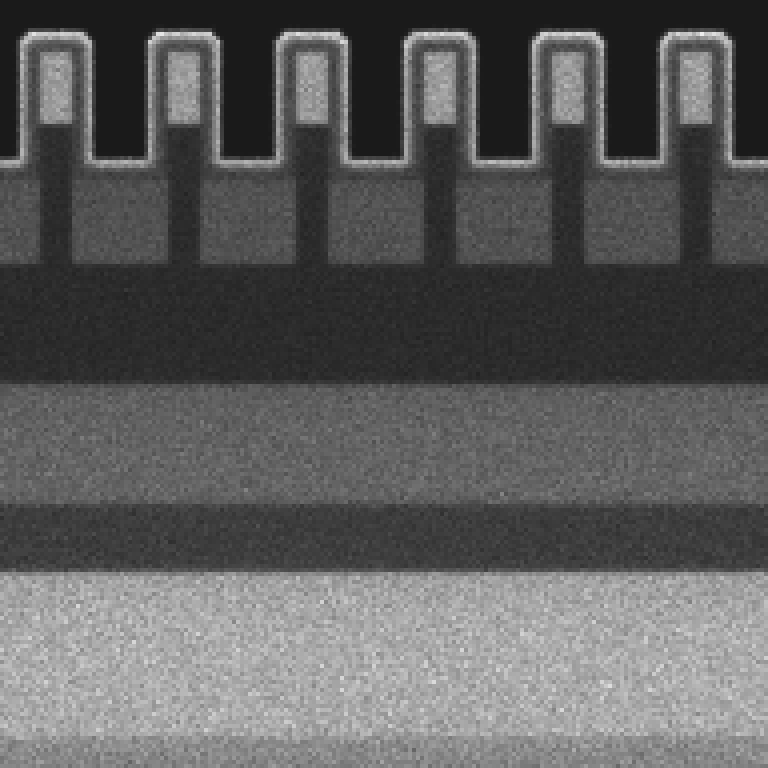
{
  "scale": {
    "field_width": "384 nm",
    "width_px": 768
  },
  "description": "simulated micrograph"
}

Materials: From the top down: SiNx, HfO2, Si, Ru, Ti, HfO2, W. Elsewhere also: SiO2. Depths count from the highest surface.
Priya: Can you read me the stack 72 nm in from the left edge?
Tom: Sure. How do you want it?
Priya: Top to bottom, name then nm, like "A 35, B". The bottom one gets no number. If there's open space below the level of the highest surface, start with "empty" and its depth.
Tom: empty 64, SiNx 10, SiO2 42, Si 60, Ru 60, Ti 34, HfO2 82, W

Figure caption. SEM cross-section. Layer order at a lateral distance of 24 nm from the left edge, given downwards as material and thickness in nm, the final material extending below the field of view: SiNx 10, HfO2 36, Si 130, Ru 60, Ti 34, HfO2 82, W